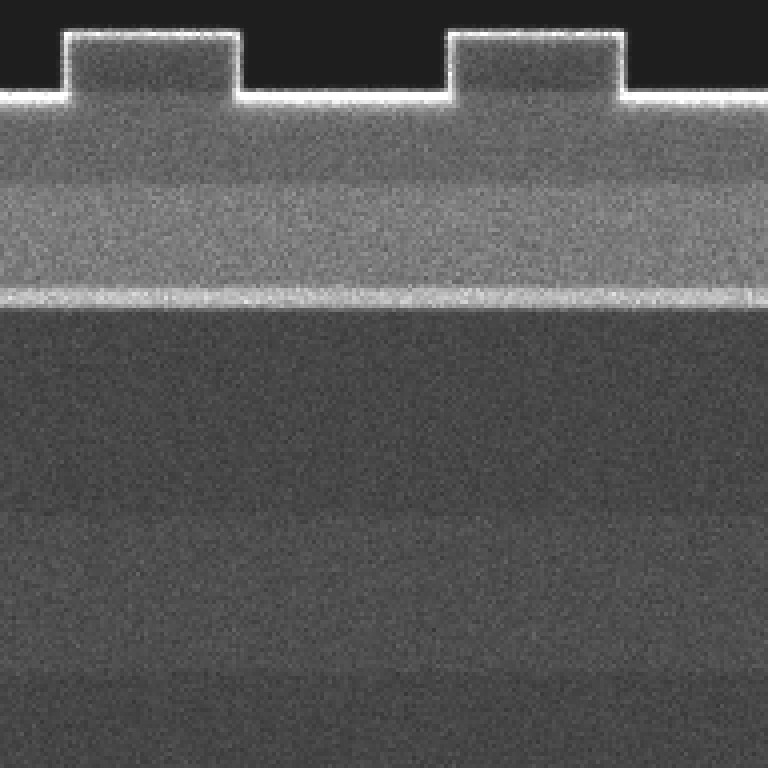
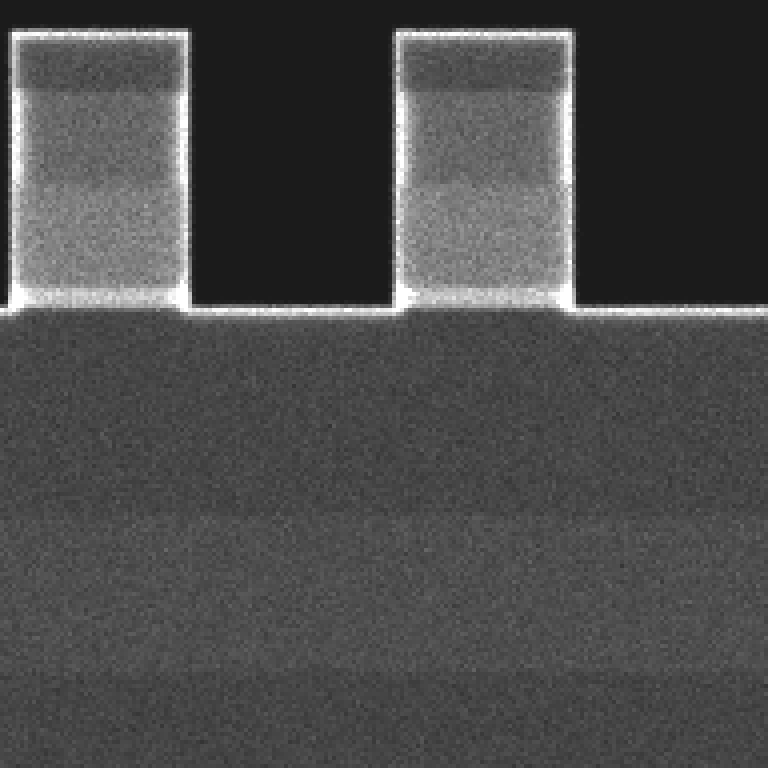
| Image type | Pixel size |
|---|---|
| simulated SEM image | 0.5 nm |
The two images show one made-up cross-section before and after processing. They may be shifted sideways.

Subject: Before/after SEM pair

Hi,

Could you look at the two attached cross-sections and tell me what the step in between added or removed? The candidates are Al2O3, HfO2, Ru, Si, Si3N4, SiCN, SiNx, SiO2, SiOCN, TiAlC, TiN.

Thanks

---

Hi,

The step removed HfO2 and Ru and SiO2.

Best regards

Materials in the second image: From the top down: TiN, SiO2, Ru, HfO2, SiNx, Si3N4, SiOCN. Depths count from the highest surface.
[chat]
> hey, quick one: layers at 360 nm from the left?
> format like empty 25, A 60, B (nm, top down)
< empty 138, SiNx 104, Si3N4 78, SiOCN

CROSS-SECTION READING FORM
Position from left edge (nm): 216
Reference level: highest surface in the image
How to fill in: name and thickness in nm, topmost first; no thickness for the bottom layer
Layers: TiN 30, SiO2 46, Ru 52, HfO2 10, SiNx 104, Si3N4 78, SiOCN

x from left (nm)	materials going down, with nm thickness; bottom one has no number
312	empty 138, SiNx 104, Si3N4 78, SiOCN